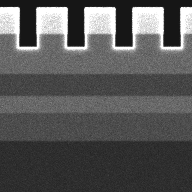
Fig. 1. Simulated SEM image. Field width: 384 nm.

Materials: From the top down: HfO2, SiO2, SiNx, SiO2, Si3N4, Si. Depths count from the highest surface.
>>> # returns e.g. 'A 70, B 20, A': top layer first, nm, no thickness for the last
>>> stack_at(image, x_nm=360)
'empty 78, SiO2 54, SiNx 44, SiO2 34, Si3N4 56, Si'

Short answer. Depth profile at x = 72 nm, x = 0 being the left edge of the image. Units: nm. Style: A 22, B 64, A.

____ empty 78, SiO2 54, SiNx 44, SiO2 34, Si3N4 56, Si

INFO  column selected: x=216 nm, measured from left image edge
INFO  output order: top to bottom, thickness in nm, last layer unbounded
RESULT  HfO2 52, SiO2 80, SiNx 44, SiO2 34, Si3N4 56, Si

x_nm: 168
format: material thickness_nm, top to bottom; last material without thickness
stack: empty 78, SiO2 54, SiNx 44, SiO2 34, Si3N4 56, Si